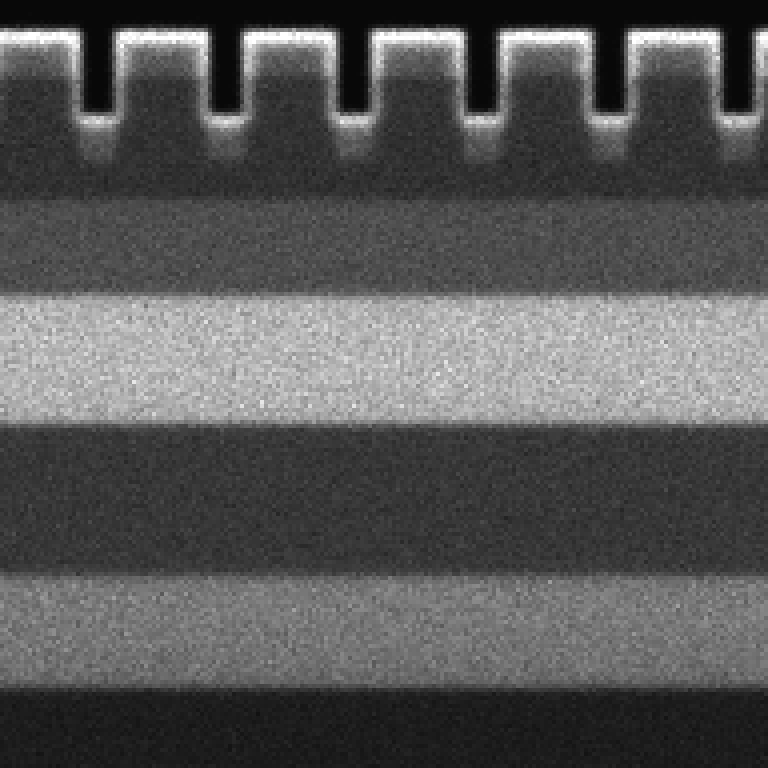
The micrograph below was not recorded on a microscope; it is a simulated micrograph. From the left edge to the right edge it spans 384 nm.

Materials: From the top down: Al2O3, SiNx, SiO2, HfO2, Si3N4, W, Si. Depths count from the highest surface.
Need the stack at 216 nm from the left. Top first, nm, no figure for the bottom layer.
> Al2O3 22, SiNx 62, SiO2 48, HfO2 64, Si3N4 76, W 56, Si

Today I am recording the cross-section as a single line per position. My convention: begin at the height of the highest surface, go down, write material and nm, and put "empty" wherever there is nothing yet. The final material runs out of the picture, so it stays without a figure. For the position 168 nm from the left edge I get empty 42, Al2O3 22, SiNx 20, SiO2 48, HfO2 64, Si3N4 76, W 56, Si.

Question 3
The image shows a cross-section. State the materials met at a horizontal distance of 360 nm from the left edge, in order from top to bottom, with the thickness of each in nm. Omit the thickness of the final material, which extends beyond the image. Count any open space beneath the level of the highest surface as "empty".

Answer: empty 42, Al2O3 22, SiNx 20, SiO2 48, HfO2 64, Si3N4 76, W 56, Si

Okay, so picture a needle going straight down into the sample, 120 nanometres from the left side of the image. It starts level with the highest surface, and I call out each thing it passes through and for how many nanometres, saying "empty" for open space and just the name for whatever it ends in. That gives empty 42, Al2O3 22, SiNx 20, SiO2 48, HfO2 64, Si3N4 76, W 56, Si